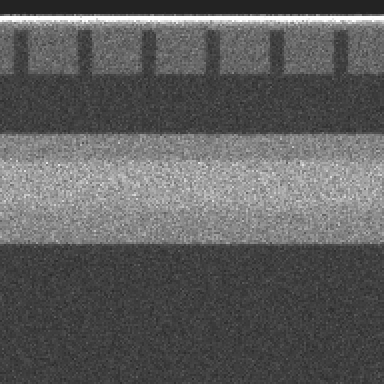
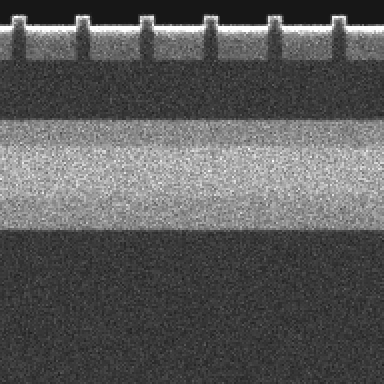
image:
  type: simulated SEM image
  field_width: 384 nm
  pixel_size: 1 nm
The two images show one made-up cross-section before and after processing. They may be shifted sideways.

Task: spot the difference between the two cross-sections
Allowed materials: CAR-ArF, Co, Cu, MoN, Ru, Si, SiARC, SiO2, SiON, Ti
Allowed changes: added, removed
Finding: removed SiARC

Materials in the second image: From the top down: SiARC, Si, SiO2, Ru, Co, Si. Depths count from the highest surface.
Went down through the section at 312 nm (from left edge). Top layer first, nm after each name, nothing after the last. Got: empty 10, SiARC 34, Si 60, SiO2 26, Ru 50, Co 34, Si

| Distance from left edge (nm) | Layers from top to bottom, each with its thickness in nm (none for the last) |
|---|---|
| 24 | Si 104, SiO2 26, Ru 50, Co 34, Si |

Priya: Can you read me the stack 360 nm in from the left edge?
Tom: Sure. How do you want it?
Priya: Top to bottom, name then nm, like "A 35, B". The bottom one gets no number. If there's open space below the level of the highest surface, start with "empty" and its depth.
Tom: empty 10, SiARC 34, Si 60, SiO2 26, Ru 50, Co 34, Si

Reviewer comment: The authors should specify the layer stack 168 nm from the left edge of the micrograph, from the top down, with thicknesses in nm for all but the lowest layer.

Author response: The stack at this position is empty 10, SiARC 34, Si 60, SiO2 26, Ru 50, Co 34, Si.